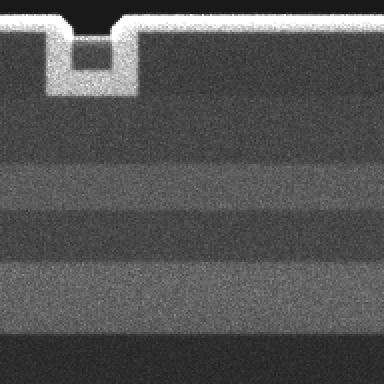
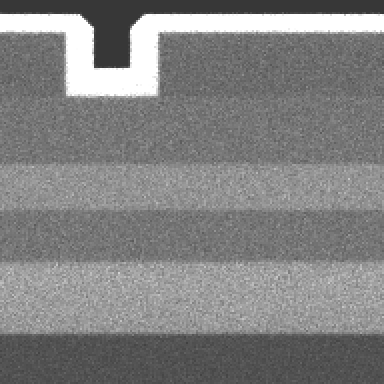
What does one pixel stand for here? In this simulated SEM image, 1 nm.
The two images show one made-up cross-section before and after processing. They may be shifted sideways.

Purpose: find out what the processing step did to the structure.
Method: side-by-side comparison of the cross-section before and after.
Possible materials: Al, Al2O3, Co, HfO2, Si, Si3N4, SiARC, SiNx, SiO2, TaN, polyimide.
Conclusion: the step removed SiARC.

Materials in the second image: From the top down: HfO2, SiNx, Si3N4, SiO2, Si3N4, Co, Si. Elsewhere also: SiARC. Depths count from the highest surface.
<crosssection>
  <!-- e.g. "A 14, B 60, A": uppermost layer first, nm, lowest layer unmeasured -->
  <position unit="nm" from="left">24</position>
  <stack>HfO2 16, SiNx 64, Si3N4 68, SiO2 46, Si3N4 52, Co 72, Si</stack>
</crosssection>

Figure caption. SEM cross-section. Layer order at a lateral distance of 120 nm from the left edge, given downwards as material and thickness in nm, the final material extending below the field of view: empty 54, HfO2 26, Si3N4 68, SiO2 46, Si3N4 52, Co 72, Si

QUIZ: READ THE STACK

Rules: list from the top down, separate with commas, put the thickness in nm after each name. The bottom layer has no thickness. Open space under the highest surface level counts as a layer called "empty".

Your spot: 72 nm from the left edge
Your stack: HfO2 80, Si3N4 68, SiO2 46, Si3N4 52, Co 72, Si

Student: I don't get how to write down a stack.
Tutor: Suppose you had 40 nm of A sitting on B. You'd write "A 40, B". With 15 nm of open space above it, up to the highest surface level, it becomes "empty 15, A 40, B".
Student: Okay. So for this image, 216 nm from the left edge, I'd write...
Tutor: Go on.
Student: HfO2 16, SiNx 64, Si3N4 68, SiO2 46, Si3N4 52, Co 72, Si